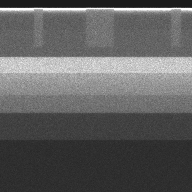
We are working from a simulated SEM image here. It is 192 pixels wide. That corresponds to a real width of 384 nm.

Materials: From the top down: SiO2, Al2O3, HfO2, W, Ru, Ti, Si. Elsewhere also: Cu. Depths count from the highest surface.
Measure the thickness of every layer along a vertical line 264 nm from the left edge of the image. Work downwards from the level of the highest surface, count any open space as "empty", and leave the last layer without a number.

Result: SiO2 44, Al2O3 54, HfO2 32, W 44, Ru 36, Ti 54, Si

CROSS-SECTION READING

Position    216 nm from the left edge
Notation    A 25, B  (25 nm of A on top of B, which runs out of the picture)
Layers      Cu 78, Al2O3 20, HfO2 32, W 44, Ru 36, Ti 54, Si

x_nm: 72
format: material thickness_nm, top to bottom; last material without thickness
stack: Cu 78, Al2O3 20, HfO2 32, W 44, Ru 36, Ti 54, Si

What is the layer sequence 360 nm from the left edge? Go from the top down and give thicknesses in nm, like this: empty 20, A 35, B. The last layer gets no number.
Cu 78, Al2O3 20, HfO2 32, W 44, Ru 36, Ti 54, Si